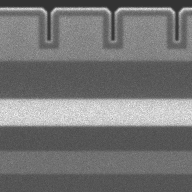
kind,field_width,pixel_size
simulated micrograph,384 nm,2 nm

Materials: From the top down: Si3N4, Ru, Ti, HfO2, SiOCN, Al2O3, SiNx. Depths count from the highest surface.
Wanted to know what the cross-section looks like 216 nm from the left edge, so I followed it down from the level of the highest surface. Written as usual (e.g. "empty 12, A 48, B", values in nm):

empty 4, Si3N4 78, Ru 24, Ti 76, HfO2 54, SiOCN 50, Al2O3 46, SiNx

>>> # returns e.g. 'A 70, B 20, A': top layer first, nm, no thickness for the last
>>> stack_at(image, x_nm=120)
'Si3N4 16, Ru 90, Ti 76, HfO2 54, SiOCN 50, Al2O3 46, SiNx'